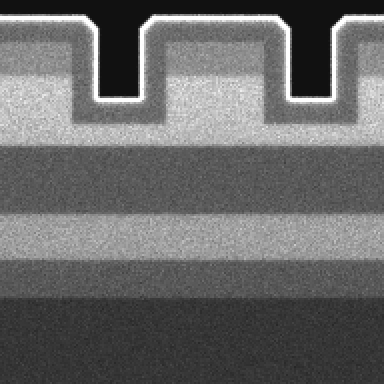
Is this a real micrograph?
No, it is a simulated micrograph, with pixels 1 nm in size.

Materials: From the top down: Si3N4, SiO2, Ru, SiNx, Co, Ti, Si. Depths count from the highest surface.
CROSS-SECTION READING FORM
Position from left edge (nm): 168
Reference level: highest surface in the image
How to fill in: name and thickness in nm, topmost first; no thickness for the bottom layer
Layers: Si3N4 26, SiO2 34, Ru 70, SiNx 68, Co 46, Ti 38, Si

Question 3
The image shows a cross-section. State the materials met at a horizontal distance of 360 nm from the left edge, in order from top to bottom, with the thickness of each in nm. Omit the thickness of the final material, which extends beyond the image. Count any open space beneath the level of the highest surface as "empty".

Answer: Si3N4 26, SiO2 34, Ru 70, SiNx 68, Co 46, Ti 38, Si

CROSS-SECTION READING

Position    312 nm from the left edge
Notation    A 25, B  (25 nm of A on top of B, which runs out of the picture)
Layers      empty 82, Si3N4 26, Ru 22, SiNx 68, Co 46, Ti 38, Si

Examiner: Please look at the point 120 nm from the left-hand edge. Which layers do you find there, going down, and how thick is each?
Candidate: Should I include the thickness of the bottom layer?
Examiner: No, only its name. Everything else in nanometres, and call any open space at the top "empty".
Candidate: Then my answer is empty 82, Si3N4 26, Ru 22, SiNx 68, Co 46, Ti 38, Si